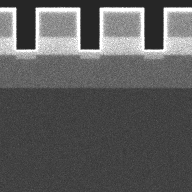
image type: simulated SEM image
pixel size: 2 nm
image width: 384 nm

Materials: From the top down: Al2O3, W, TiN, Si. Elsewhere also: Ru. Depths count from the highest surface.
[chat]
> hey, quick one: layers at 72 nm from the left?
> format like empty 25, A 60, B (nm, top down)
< Al2O3 58, W 36, TiN 66, Si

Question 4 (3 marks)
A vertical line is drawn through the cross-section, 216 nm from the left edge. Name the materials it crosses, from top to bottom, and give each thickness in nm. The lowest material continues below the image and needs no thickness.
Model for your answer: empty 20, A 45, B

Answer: Al2O3 58, W 36, TiN 66, Si